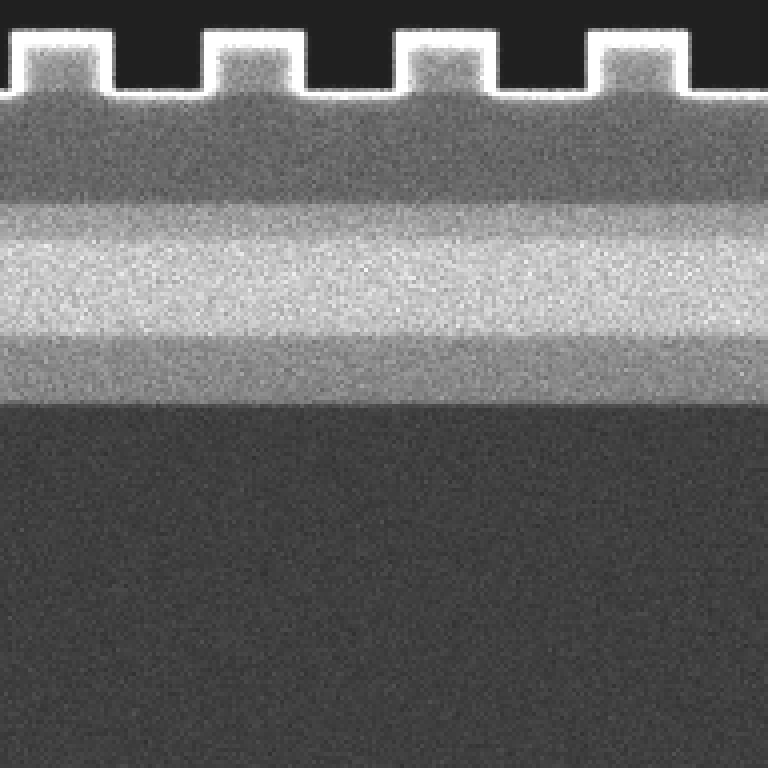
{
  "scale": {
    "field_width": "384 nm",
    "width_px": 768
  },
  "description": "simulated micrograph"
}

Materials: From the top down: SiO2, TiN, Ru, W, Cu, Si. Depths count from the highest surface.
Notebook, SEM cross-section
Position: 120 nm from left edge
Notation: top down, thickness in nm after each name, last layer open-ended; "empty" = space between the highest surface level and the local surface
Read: SiO2 30, TiN 56, Ru 18, W 48, Cu 34, Si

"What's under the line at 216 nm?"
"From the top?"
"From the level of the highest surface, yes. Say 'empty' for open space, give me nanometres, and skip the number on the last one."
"SiO2 30, TiN 56, Ru 18, W 48, Cu 34, Si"